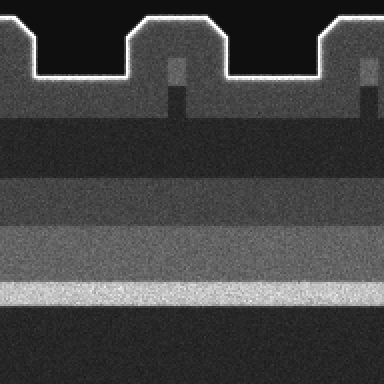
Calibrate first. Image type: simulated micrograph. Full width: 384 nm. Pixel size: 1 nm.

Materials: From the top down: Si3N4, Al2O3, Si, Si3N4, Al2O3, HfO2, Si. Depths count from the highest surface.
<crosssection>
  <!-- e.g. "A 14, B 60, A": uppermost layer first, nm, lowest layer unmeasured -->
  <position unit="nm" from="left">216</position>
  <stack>empty 10, Si3N4 92, Si 60, Si3N4 48, Al2O3 56, HfO2 24, Si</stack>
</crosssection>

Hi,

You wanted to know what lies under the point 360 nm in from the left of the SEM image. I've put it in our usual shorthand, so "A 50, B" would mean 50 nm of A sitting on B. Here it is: Si3N4 42, Al2O3 28, Si 92, Si3N4 48, Al2O3 56, HfO2 24, Si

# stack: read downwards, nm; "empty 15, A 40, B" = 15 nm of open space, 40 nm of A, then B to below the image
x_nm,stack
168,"Si3N4 42, Al2O3 28, Si 92, Si3N4 48, Al2O3 56, HfO2 24, Si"